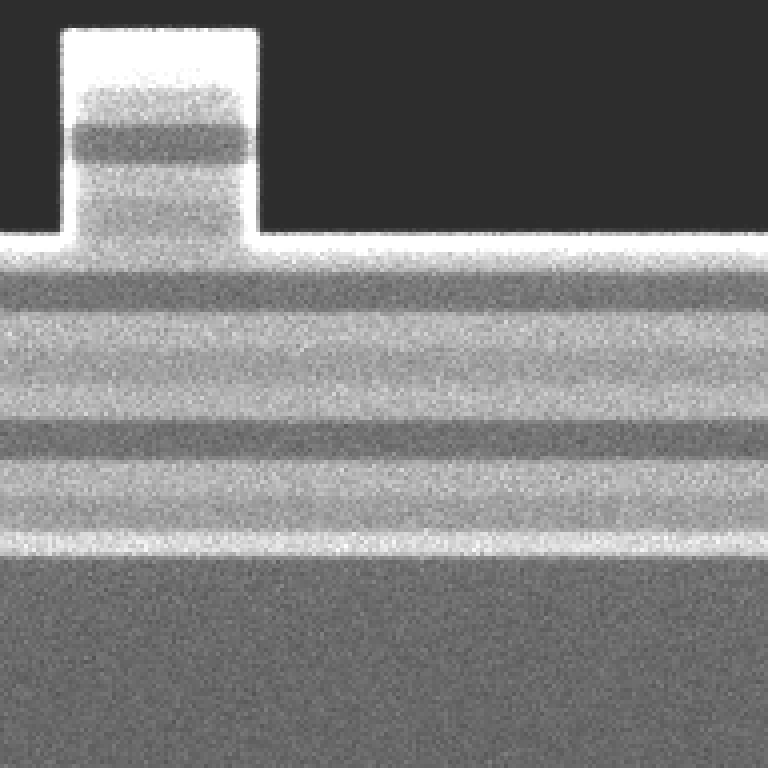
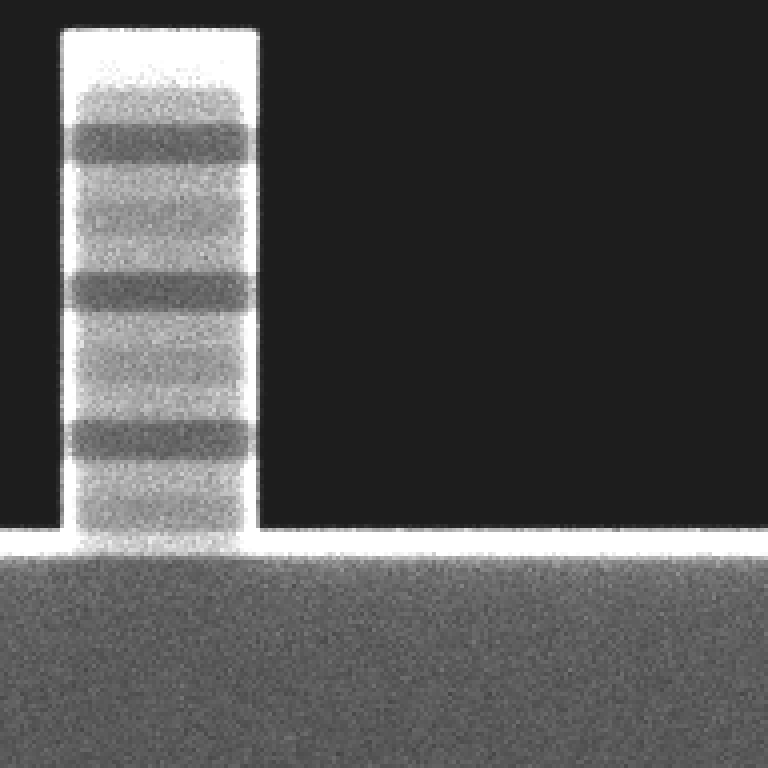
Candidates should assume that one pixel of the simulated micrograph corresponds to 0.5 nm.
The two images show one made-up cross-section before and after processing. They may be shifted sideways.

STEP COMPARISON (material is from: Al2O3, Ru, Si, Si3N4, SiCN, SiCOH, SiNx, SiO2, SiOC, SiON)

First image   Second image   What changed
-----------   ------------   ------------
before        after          Si and Si3N4 and SiNx, removed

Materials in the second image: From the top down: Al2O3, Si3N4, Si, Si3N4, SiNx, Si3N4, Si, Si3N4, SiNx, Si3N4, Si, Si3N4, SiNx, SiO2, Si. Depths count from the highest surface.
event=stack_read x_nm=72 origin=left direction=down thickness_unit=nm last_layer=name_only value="Al2O3 28, Si3N4 18, Si 20, Si3N4 18, SiNx 18, Si3N4 18, Si 20, Si3N4 18, SiNx 18, Si3N4 18, Si 20, Si3N4 18, SiNx 18, SiO2 12, Si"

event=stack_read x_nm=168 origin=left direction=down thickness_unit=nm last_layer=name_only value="empty 250, SiO2 12, Si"